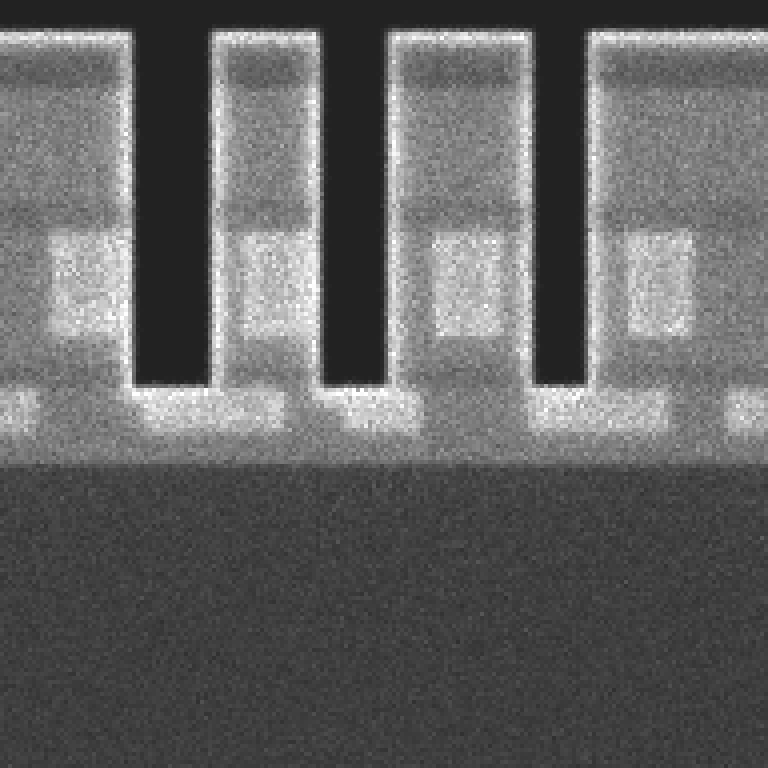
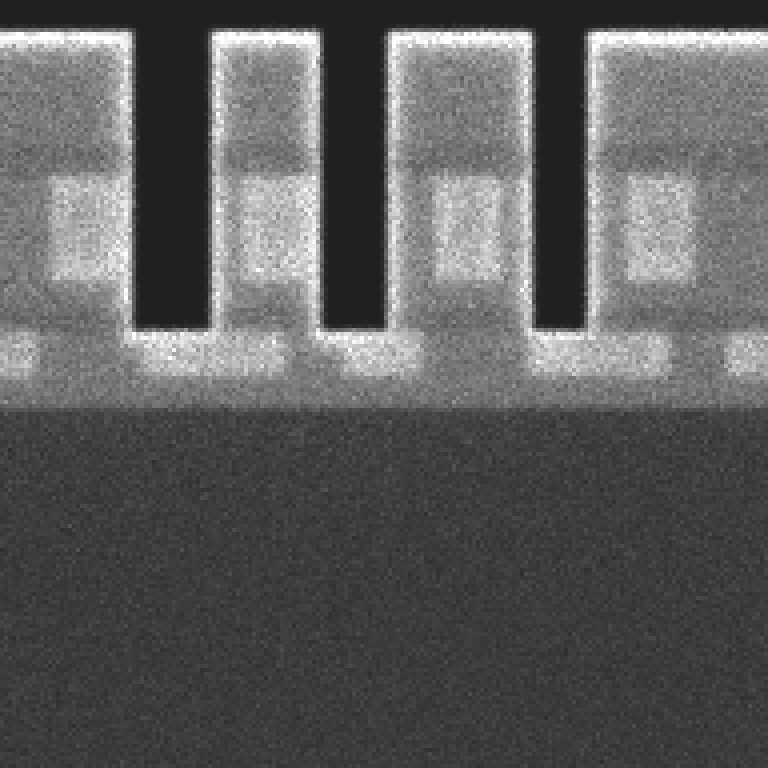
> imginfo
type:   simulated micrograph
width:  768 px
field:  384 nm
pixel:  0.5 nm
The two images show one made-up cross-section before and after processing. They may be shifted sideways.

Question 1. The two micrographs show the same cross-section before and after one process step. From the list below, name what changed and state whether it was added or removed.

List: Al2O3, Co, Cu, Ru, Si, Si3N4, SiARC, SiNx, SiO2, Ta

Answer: SiARC, removed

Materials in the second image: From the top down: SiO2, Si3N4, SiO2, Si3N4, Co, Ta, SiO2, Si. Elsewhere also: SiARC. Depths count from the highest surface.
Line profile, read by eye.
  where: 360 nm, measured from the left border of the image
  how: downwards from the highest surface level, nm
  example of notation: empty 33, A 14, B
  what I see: SiO2 56, Si3N4 16, SiO2 66, Si3N4 12, SiO2 38, Si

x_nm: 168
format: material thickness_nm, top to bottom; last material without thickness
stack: empty 150, SiO2 38, Si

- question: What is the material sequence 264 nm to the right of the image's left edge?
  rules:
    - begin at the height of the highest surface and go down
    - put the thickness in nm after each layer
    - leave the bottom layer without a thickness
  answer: SiO2 56, Si3N4 16, SiO2 66, Si3N4 12, Ta 22, SiO2 16, Si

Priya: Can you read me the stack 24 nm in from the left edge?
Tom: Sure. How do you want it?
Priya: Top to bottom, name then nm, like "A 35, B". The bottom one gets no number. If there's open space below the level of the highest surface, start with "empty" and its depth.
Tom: SiO2 56, Si3N4 16, SiO2 66, Si3N4 12, SiO2 38, Si